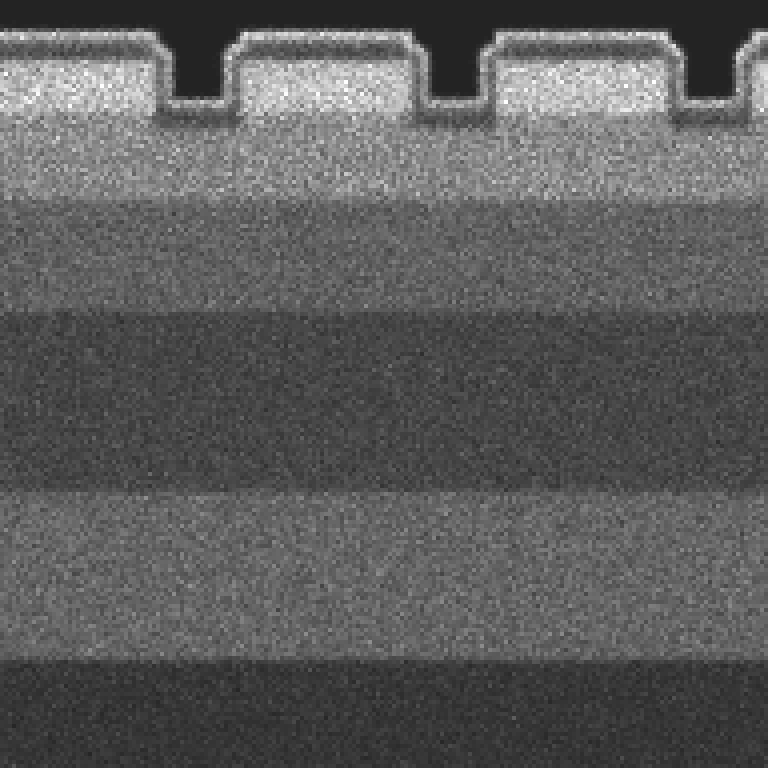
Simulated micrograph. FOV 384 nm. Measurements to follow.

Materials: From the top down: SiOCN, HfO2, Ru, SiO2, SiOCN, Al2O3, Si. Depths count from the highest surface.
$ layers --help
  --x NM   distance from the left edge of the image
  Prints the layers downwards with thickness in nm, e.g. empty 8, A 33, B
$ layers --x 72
SiOCN 14, HfO2 26, Ru 44, SiO2 56, SiOCN 90, Al2O3 84, Si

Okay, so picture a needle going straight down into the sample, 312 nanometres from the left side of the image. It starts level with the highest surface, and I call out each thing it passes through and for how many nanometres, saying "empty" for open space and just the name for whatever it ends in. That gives SiOCN 14, HfO2 26, Ru 44, SiO2 56, SiOCN 90, Al2O3 84, Si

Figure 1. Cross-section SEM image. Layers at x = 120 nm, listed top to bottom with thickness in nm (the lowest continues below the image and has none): SiOCN 14, HfO2 26, Ru 44, SiO2 56, SiOCN 90, Al2O3 84, Si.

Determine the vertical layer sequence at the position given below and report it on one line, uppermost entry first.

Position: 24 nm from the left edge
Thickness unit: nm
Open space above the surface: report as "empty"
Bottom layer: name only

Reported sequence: SiOCN 14, HfO2 26, Ru 44, SiO2 56, SiOCN 90, Al2O3 84, Si